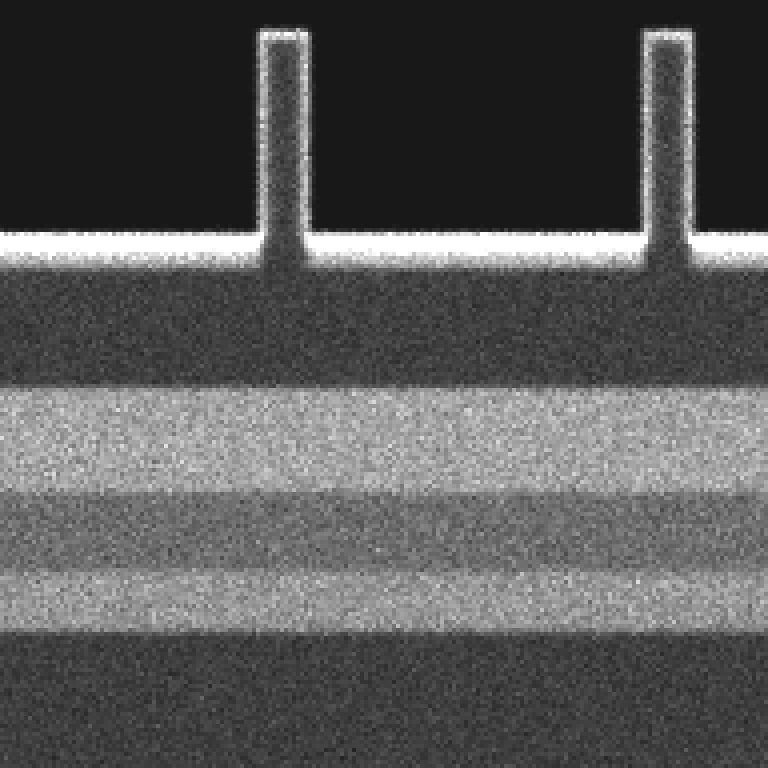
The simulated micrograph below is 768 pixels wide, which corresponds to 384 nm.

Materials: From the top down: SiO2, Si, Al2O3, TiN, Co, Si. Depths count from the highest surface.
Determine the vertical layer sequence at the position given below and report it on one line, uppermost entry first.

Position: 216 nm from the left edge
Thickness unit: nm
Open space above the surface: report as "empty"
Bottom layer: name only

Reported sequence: empty 102, SiO2 16, Si 60, Al2O3 52, TiN 40, Co 30, Si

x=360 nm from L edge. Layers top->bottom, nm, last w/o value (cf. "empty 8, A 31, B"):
empty 102, SiO2 16, Si 60, Al2O3 52, TiN 40, Co 30, Si